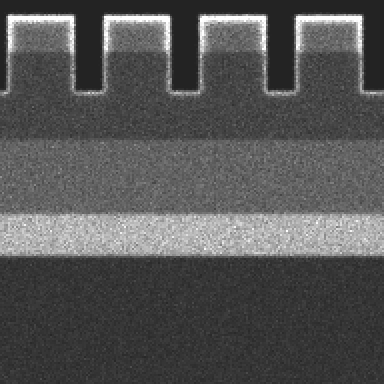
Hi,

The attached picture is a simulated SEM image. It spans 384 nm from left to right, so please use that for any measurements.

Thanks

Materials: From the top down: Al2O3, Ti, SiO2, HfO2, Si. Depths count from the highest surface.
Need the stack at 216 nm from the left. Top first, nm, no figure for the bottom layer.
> Al2O3 36, Ti 88, SiO2 74, HfO2 42, Si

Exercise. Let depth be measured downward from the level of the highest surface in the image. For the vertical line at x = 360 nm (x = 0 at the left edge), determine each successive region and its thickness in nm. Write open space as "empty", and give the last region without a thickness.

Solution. Al2O3 36, Ti 88, SiO2 74, HfO2 42, Si